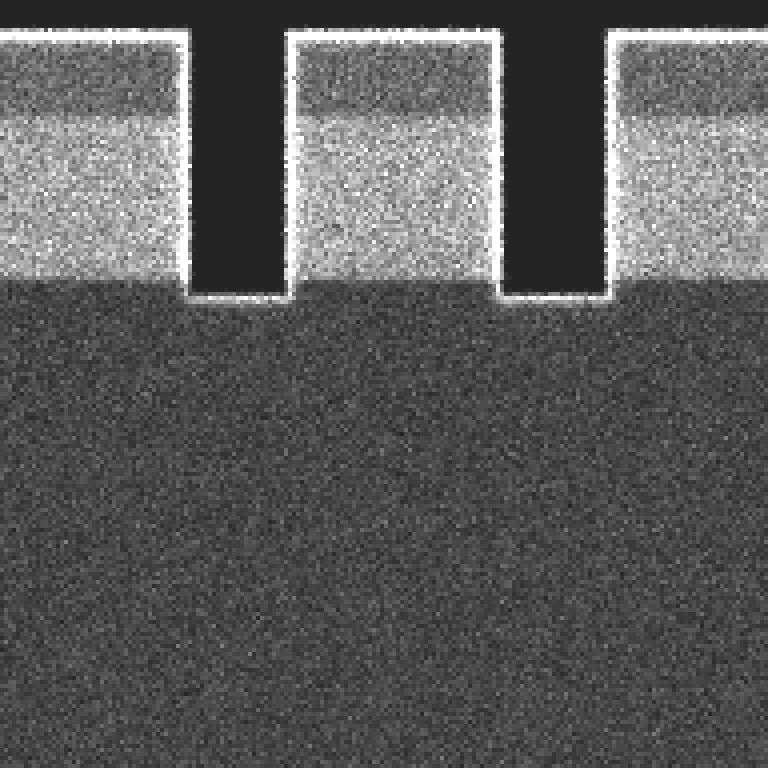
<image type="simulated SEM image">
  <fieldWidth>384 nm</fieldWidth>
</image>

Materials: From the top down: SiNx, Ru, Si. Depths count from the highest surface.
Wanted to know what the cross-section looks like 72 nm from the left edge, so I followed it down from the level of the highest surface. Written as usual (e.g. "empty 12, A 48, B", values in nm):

SiNx 42, Ru 82, Si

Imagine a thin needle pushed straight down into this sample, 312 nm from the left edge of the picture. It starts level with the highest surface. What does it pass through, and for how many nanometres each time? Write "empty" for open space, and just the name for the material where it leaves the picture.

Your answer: SiNx 42, Ru 82, Si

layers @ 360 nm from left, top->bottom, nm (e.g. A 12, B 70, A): SiNx 42, Ru 82, Si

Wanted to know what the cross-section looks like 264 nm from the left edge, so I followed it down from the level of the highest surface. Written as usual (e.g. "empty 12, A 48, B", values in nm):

empty 132, Si